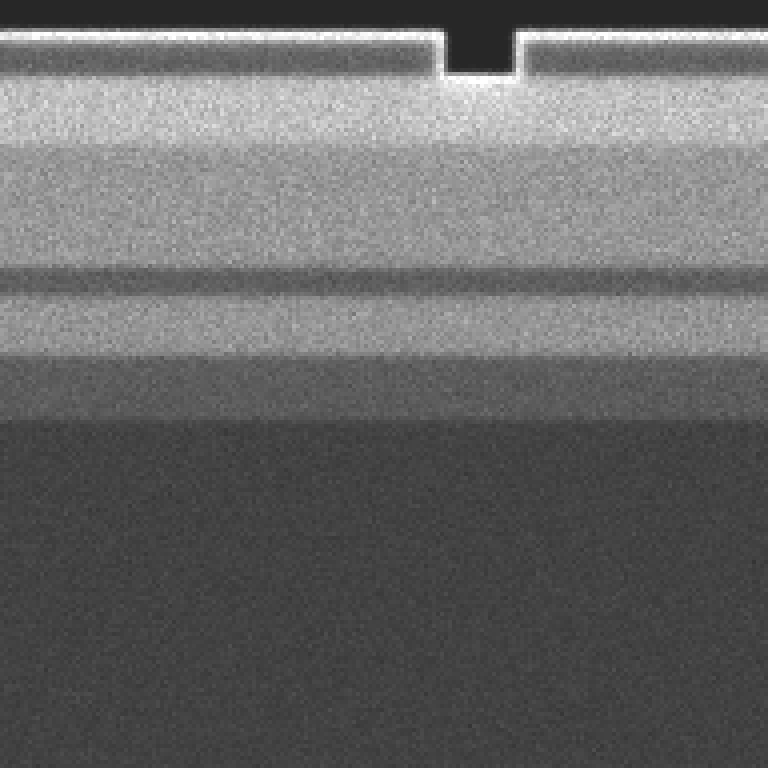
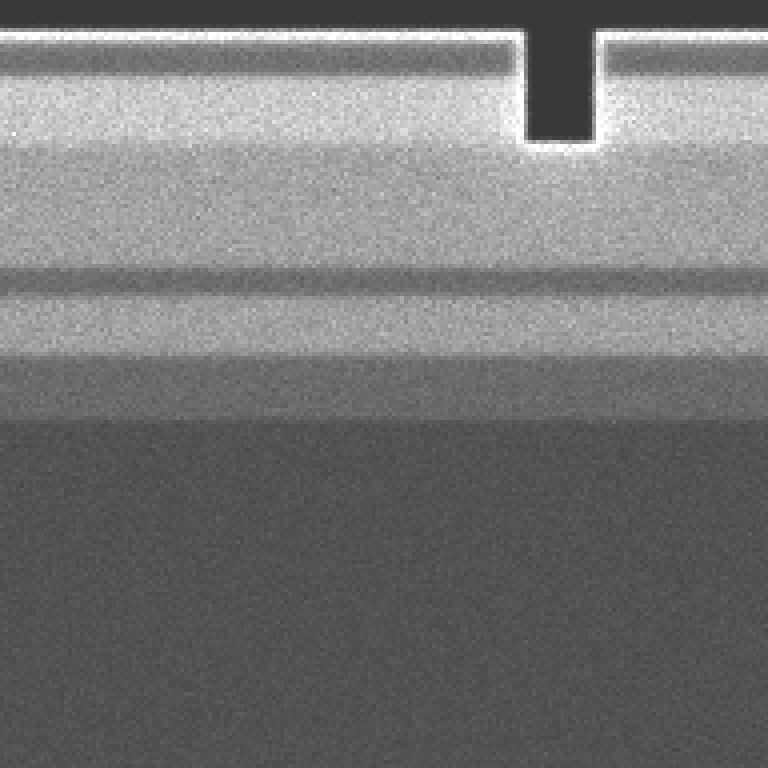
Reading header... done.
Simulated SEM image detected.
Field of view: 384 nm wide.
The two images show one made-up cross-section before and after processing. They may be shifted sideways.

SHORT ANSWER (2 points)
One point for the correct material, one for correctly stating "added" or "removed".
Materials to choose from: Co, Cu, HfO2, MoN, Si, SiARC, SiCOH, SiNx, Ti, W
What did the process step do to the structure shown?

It removed W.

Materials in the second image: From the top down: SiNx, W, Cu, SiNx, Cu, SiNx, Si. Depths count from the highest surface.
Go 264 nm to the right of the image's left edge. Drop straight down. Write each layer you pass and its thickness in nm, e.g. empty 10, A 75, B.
empty 56, Cu 62, SiNx 14, Cu 30, SiNx 32, Si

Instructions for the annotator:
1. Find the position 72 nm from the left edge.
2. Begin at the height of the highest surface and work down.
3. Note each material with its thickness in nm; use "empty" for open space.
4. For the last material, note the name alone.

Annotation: SiNx 22, W 34, Cu 62, SiNx 14, Cu 30, SiNx 32, Si